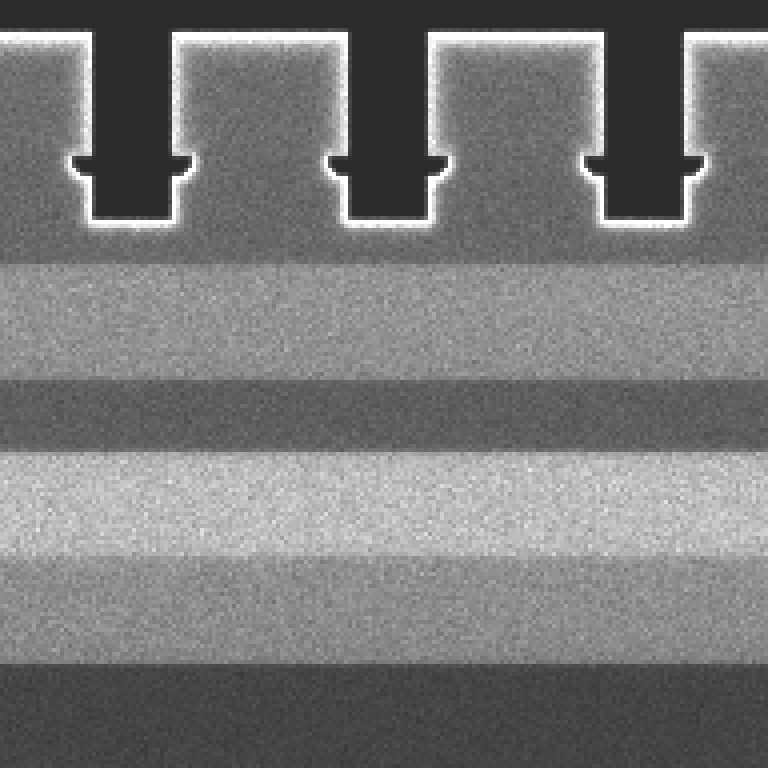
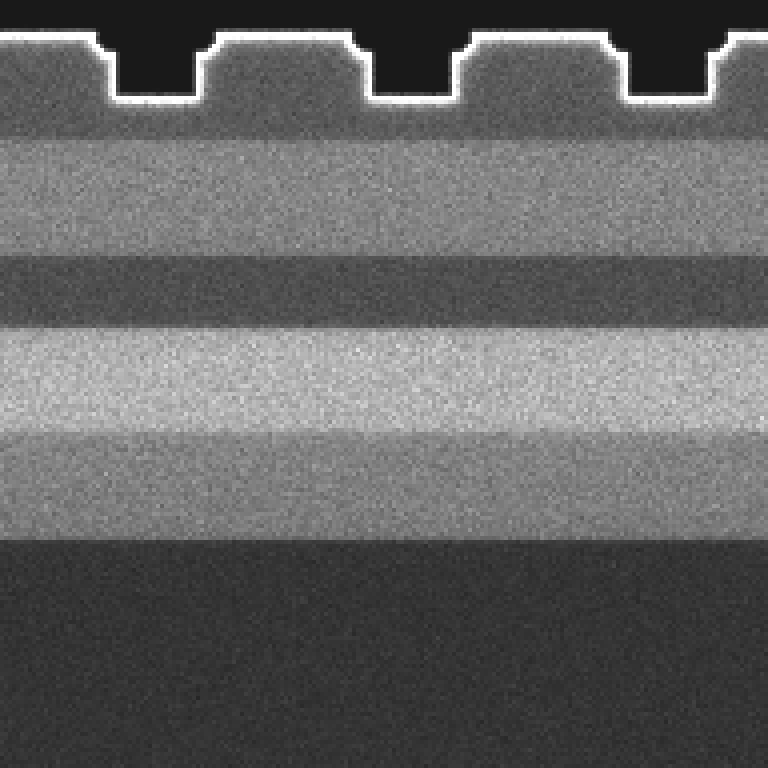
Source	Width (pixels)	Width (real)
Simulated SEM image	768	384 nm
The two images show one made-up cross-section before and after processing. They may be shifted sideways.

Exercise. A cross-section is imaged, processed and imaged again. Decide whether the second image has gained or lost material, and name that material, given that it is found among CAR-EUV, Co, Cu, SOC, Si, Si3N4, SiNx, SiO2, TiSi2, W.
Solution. removed: SOC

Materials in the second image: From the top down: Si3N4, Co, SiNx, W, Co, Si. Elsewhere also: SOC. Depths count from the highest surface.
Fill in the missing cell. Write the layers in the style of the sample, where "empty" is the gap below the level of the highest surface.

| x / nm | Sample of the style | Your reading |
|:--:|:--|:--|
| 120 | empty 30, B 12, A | Si3N4 54, Co 58, SiNx 36, W 52, Co 54, Si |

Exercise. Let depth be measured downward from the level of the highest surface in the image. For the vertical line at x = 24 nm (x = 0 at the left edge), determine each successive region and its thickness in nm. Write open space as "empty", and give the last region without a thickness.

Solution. Si3N4 54, Co 58, SiNx 36, W 52, Co 54, Si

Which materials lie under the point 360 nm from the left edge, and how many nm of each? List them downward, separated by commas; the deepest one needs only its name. empty 8, Si3N4 46, Co 58, SiNx 36, W 52, Co 54, Si